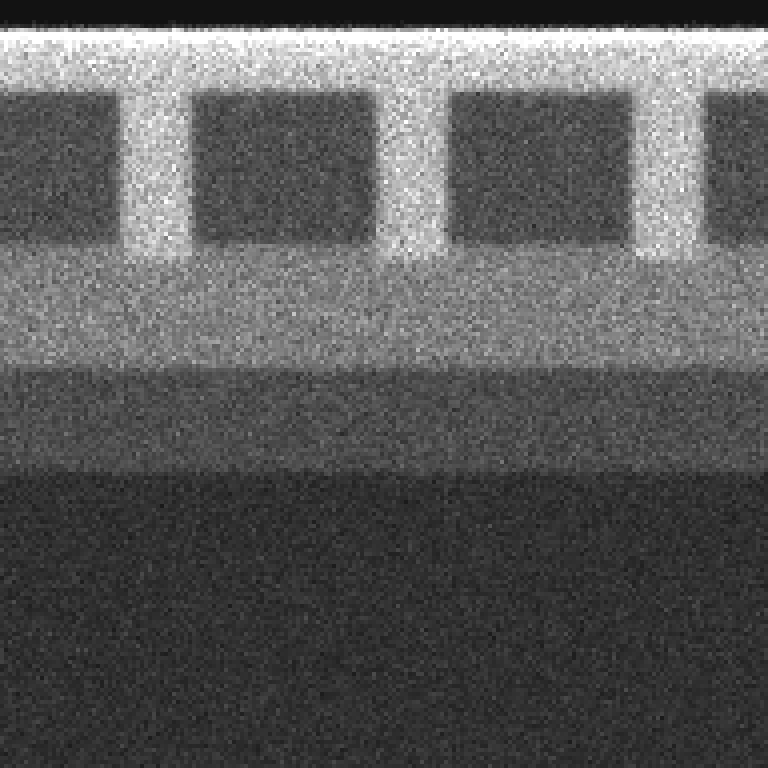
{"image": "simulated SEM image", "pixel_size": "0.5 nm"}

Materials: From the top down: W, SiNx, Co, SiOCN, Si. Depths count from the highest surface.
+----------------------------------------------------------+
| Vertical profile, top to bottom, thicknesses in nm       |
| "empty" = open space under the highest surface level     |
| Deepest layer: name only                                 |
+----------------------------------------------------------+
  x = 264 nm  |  W 30, SiNx 76, Co 62, SiOCN 52, Si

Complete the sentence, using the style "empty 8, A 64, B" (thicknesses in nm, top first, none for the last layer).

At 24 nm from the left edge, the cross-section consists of W 30, SiNx 76, Co 62, SiOCN 52, Si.